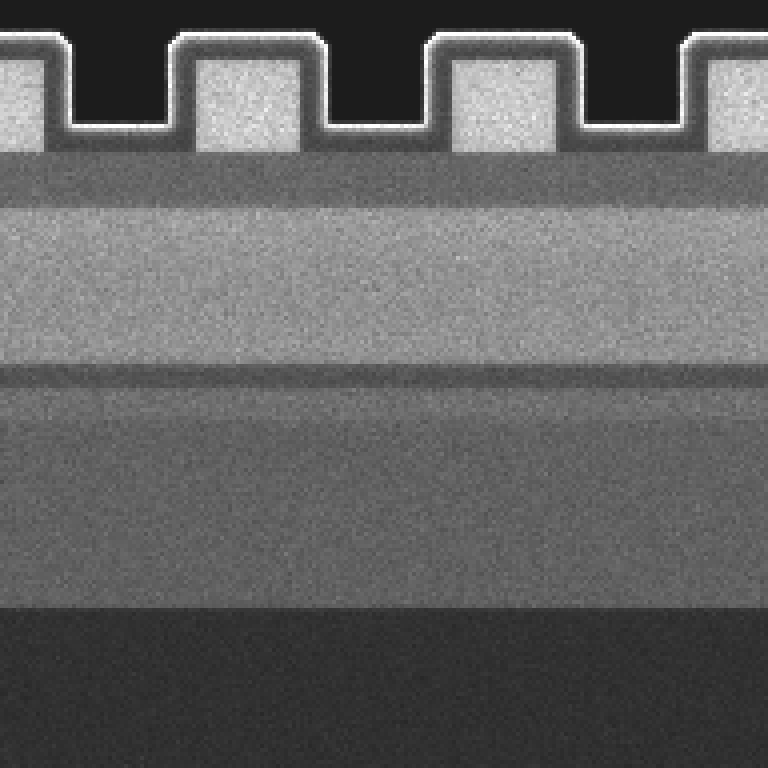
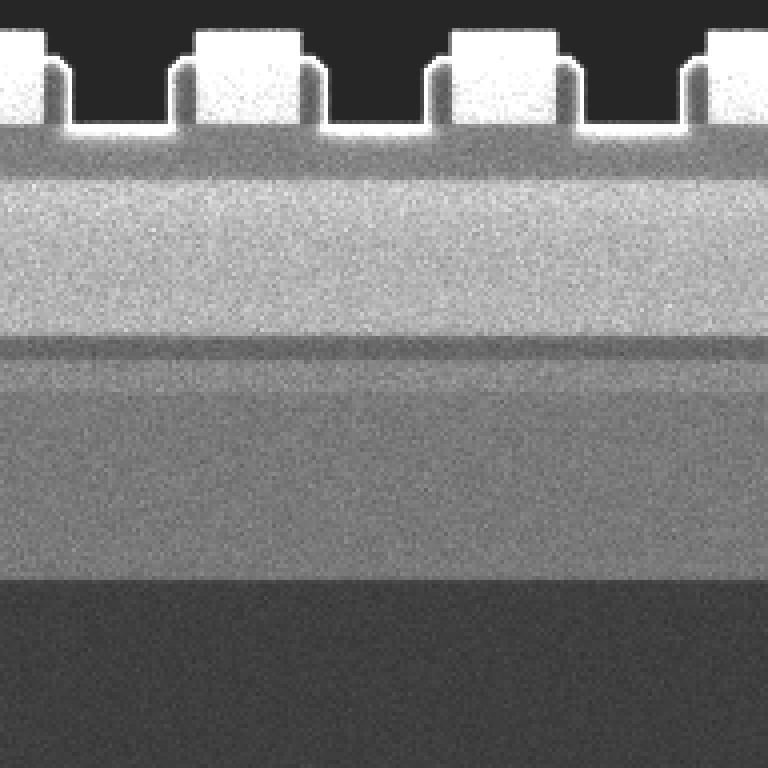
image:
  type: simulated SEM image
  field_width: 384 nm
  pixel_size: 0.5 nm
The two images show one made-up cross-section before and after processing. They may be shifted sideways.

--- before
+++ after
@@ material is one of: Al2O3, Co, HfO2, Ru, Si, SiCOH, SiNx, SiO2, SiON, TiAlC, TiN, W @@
SiNx removed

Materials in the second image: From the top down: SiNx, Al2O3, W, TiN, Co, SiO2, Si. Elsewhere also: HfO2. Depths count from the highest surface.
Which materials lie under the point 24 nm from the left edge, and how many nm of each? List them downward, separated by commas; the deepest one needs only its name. empty 12, SiNx 34, Al2O3 28, W 78, TiN 12, Co 16, SiO2 94, Si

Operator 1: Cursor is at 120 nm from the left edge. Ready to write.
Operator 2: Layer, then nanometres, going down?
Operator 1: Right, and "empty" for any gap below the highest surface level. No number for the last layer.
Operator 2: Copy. HfO2 46, Al2O3 28, W 78, TiN 12, Co 16, SiO2 94, Si